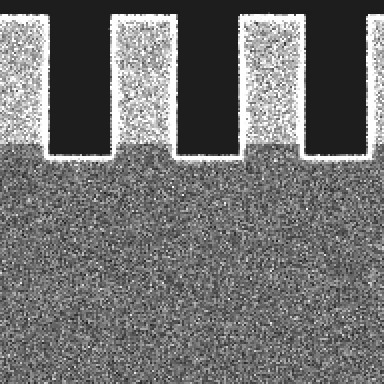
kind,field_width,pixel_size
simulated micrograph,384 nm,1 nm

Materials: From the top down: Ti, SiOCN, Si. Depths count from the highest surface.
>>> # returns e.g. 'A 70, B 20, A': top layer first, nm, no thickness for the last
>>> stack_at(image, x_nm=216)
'empty 140, Si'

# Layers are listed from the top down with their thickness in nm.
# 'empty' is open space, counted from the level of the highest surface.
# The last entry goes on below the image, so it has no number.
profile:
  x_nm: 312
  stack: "empty 140, Si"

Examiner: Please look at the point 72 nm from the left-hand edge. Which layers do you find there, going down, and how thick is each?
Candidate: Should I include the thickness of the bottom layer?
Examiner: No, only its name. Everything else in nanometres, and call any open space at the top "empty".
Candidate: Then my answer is empty 140, Si